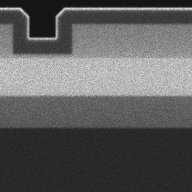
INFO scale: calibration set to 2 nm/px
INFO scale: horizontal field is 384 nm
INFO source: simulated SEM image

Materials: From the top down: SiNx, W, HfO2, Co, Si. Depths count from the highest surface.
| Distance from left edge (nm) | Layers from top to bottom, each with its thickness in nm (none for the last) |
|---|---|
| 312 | SiNx 32, W 68, HfO2 76, Co 64, Si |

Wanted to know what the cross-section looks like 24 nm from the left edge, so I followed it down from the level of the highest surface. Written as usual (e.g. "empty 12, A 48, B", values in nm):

SiNx 32, W 68, HfO2 76, Co 64, Si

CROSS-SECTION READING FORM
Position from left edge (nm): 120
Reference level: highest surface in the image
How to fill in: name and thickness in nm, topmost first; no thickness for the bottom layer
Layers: empty 8, SiNx 84, W 8, HfO2 76, Co 64, Si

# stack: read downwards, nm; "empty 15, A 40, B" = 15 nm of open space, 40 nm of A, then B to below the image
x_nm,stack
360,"SiNx 32, W 68, HfO2 76, Co 64, Si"